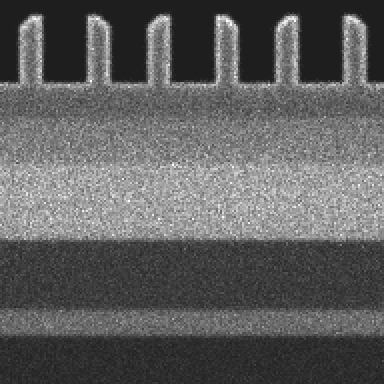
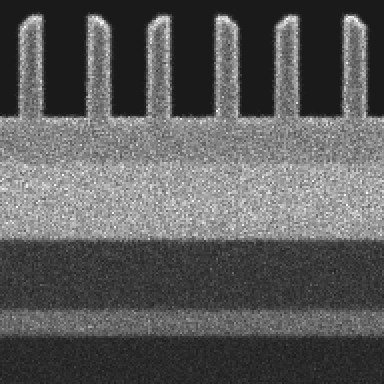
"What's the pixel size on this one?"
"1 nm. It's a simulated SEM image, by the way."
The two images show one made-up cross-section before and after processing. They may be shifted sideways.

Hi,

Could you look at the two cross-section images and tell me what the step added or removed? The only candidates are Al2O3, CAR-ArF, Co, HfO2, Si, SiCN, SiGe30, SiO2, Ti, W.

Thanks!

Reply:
removed Co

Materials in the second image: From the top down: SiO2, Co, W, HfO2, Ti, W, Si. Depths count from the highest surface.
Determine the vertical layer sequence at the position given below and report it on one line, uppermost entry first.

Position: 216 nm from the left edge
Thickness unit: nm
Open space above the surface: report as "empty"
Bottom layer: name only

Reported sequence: SiO2 68, Co 34, W 46, HfO2 76, Ti 70, W 26, Si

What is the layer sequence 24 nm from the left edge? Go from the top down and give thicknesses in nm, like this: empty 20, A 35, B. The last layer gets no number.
empty 6, SiO2 62, Co 34, W 46, HfO2 76, Ti 70, W 26, Si